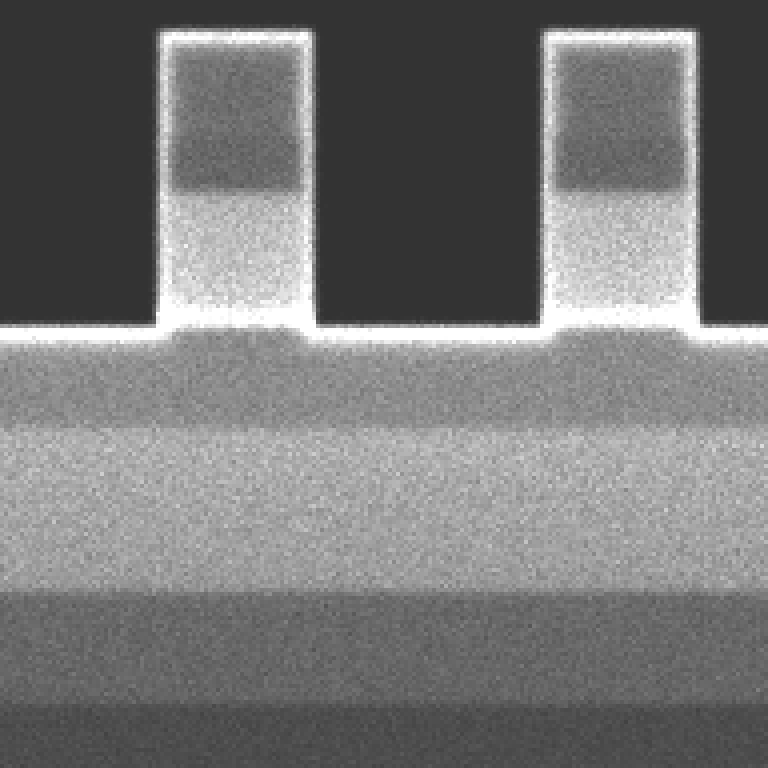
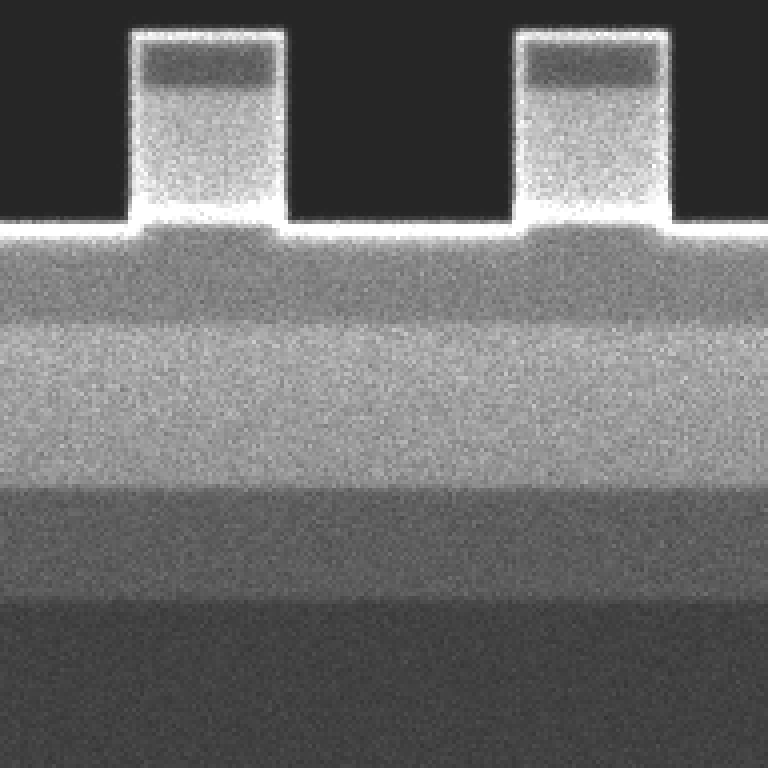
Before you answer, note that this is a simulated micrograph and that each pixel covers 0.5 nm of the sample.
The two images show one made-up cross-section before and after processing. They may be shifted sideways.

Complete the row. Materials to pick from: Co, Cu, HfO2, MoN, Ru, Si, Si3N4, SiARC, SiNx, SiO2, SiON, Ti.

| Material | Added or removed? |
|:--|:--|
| SiARC | removed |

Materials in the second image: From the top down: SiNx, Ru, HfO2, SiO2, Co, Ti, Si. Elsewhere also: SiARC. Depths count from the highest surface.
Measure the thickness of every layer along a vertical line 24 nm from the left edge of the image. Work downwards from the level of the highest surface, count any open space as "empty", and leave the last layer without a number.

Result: empty 96, SiO2 50, Co 82, Ti 56, Si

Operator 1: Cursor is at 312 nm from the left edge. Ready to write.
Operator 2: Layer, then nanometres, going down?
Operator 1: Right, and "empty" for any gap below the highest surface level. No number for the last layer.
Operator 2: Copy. SiNx 28, Ru 58, HfO2 10, SiO2 50, Co 82, Ti 56, Si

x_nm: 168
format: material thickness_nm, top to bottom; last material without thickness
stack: empty 96, SiO2 50, Co 82, Ti 56, Si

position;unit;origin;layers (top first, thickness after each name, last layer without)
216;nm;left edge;empty 96, SiO2 50, Co 82, Ti 56, Si